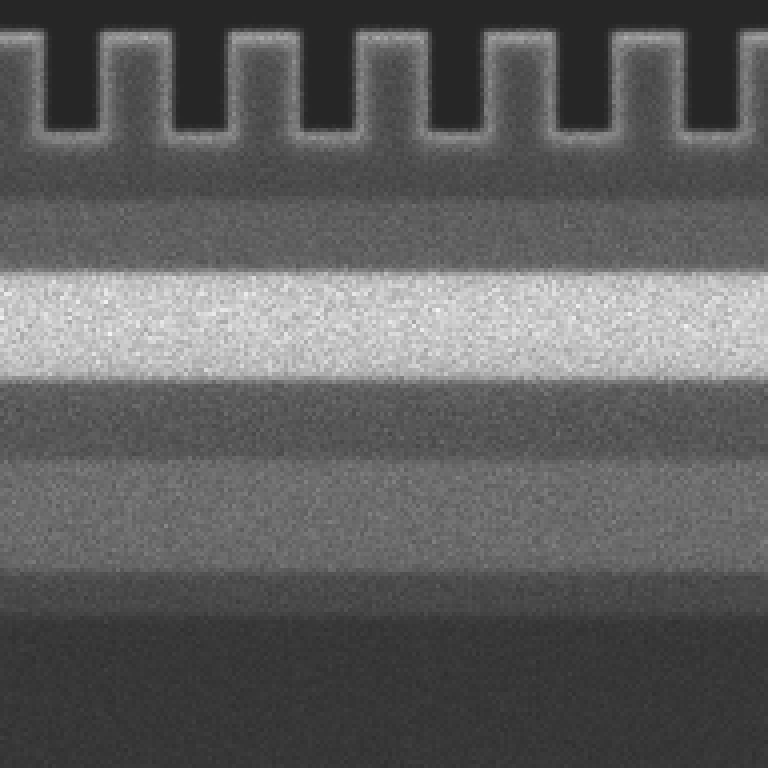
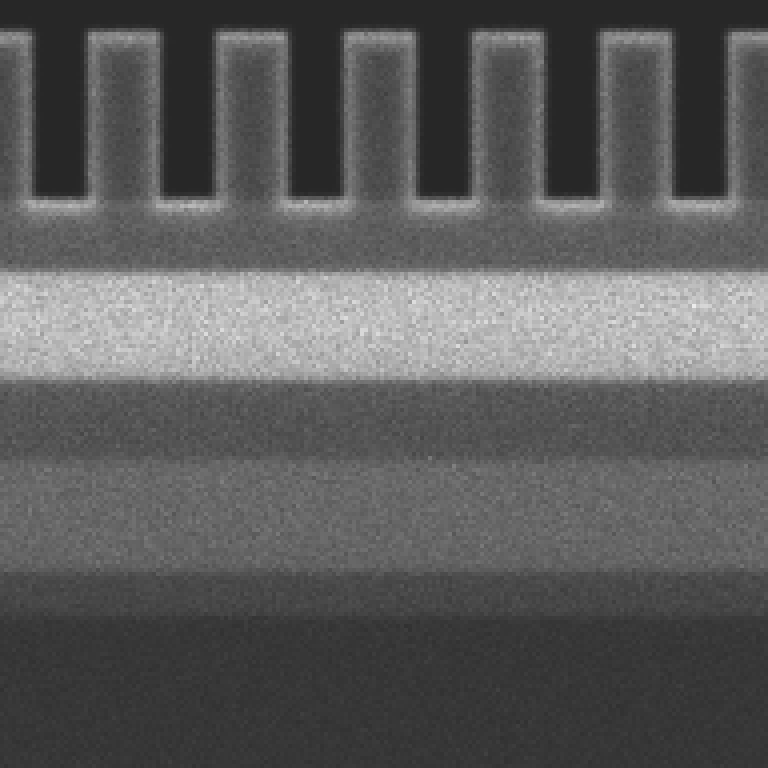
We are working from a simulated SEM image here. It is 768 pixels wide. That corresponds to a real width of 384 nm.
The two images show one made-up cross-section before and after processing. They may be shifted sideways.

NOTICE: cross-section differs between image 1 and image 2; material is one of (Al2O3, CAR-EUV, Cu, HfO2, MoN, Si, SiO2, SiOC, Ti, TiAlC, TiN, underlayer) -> removed: underlayer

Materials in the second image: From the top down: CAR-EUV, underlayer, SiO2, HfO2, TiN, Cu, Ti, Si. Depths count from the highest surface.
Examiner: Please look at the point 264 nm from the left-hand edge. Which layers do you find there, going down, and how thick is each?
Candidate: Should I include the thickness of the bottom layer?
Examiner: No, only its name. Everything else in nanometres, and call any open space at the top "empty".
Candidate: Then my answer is CAR-EUV 50, underlayer 34, SiO2 36, HfO2 54, TiN 40, Cu 56, Ti 22, Si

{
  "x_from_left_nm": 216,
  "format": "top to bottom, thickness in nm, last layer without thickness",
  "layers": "empty 84, SiO2 36, HfO2 54, TiN 40, Cu 56, Ti 22, Si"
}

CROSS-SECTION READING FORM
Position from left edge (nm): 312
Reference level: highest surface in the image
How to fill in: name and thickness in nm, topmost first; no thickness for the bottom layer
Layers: CAR-EUV 50, underlayer 34, SiO2 36, HfO2 54, TiN 40, Cu 56, Ti 22, Si